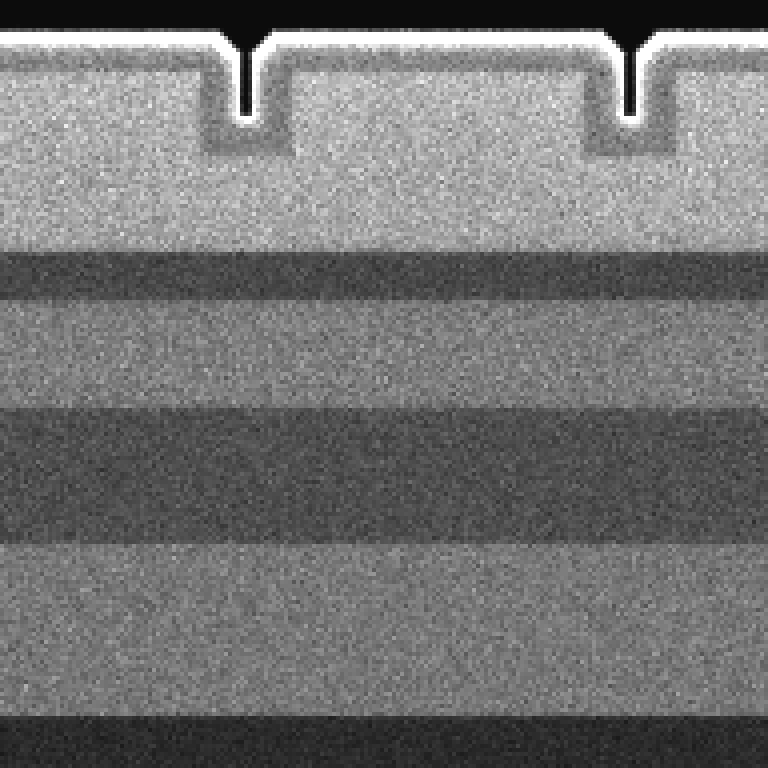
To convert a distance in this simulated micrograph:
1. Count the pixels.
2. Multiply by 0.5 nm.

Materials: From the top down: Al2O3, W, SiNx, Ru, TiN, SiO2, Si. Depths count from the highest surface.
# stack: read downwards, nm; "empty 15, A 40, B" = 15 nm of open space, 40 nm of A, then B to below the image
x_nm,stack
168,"Al2O3 20, W 90, SiNx 24, Ru 54, TiN 68, SiO2 86, Si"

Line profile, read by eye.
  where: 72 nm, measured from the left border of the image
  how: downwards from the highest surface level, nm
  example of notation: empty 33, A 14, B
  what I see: Al2O3 20, W 90, SiNx 24, Ru 54, TiN 68, SiO2 86, Si